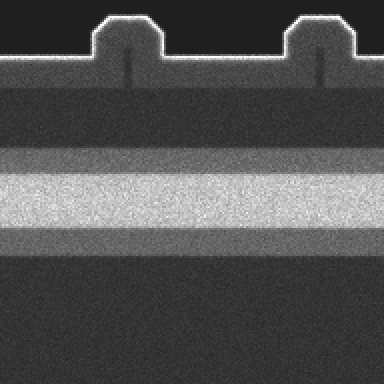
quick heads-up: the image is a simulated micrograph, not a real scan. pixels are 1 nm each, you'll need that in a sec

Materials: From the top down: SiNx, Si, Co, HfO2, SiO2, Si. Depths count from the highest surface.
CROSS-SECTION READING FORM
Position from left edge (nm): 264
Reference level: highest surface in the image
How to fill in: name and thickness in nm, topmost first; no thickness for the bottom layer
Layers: empty 40, SiNx 32, Si 60, Co 26, HfO2 54, SiO2 28, Si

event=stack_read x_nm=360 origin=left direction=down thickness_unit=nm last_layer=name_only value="empty 40, SiNx 32, Si 60, Co 26, HfO2 54, SiO2 28, Si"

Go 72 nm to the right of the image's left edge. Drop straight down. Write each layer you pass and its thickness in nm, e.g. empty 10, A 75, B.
empty 40, SiNx 32, Si 60, Co 26, HfO2 54, SiO2 28, Si